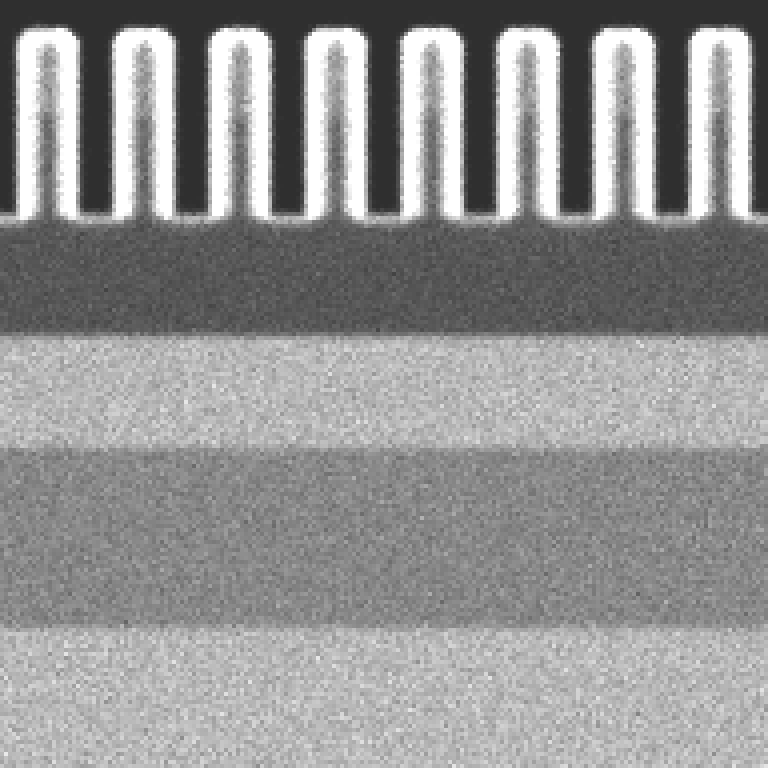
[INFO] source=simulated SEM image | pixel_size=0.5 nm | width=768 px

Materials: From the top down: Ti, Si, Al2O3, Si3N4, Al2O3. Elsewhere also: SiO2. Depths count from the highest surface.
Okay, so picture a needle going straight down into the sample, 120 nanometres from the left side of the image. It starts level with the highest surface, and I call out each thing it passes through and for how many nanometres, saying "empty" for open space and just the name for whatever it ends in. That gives Ti 42, Si 110, Al2O3 56, Si3N4 90, Al2O3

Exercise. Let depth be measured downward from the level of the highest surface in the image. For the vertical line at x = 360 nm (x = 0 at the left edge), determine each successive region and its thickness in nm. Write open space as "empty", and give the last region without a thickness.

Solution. Ti 42, Si 110, Al2O3 56, Si3N4 90, Al2O3